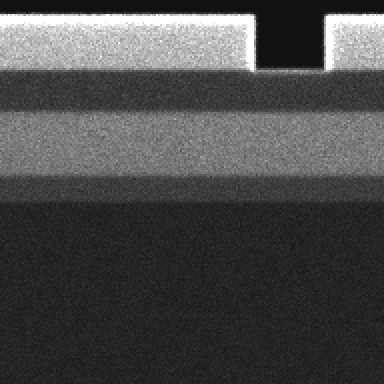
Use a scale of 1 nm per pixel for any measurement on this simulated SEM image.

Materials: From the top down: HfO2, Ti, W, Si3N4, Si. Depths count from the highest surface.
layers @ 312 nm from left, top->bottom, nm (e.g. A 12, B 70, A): empty 54, Ti 42, W 64, Si3N4 26, Si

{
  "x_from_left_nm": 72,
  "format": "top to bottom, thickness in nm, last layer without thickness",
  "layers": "HfO2 54, Ti 42, W 64, Si3N4 26, Si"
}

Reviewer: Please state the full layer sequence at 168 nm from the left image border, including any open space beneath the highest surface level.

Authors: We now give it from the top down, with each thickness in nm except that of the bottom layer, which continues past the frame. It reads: HfO2 54, Ti 42, W 64, Si3N4 26, Si